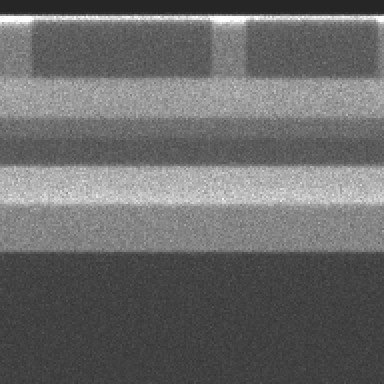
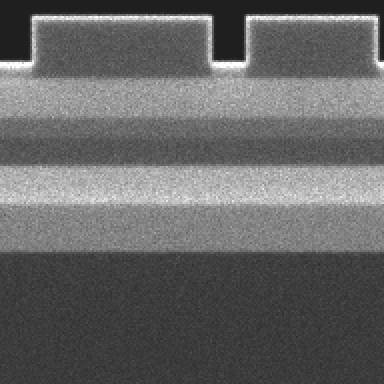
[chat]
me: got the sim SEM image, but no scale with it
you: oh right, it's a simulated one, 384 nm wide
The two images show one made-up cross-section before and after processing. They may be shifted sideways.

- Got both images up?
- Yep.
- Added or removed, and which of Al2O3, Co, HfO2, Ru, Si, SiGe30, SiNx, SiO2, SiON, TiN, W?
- removed, SiO2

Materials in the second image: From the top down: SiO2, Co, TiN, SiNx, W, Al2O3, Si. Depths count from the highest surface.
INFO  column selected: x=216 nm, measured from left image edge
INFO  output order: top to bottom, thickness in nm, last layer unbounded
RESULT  empty 46, SiO2 16, Co 40, TiN 20, SiNx 28, W 38, Al2O3 48, Si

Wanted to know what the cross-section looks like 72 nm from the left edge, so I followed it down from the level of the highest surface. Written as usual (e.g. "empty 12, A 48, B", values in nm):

SiNx 62, Co 40, TiN 20, SiNx 28, W 38, Al2O3 48, Si